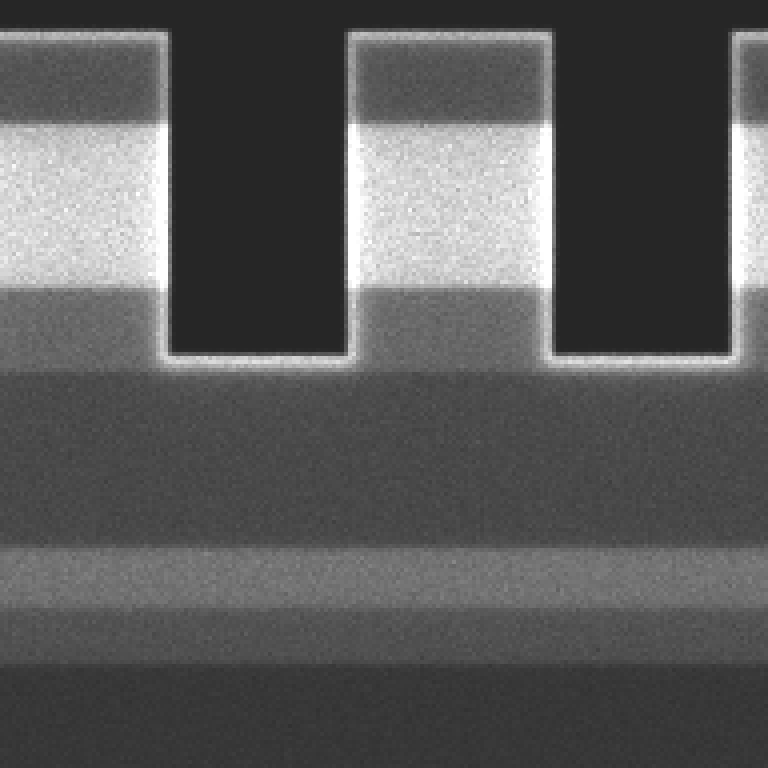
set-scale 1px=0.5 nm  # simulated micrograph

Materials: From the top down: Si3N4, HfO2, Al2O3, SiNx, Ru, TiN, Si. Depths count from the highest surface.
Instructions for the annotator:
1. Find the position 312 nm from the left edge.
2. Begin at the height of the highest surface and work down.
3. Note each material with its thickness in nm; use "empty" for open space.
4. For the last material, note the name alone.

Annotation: empty 162, Al2O3 8, SiNx 88, Ru 30, TiN 28, Si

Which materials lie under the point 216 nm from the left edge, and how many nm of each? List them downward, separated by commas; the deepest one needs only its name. Si3N4 46, HfO2 82, Al2O3 42, SiNx 88, Ru 30, TiN 28, Si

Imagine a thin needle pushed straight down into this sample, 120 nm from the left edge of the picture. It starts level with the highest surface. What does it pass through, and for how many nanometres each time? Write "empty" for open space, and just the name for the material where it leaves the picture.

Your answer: empty 162, Al2O3 8, SiNx 88, Ru 30, TiN 28, Si